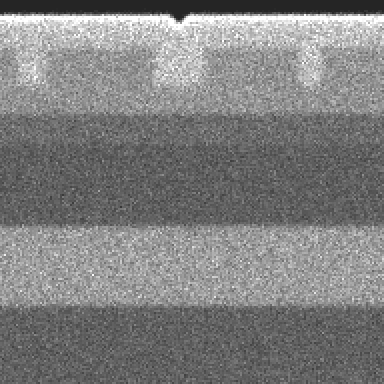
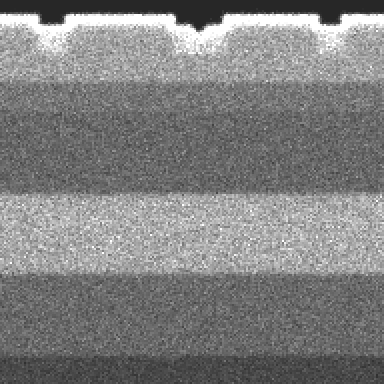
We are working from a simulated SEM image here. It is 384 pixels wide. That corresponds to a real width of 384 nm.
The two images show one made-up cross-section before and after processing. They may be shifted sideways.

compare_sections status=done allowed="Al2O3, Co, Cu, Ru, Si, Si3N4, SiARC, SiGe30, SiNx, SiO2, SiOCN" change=removed material="Ru"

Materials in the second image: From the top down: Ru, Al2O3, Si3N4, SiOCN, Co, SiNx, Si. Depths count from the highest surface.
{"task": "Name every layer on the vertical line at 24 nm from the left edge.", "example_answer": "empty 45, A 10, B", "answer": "Al2O3 66, Si3N4 30, SiOCN 82, Co 80, SiNx 82, Si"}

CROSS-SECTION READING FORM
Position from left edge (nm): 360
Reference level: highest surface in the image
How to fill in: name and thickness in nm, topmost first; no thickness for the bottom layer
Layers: Al2O3 66, Si3N4 30, SiOCN 82, Co 80, SiNx 82, Si